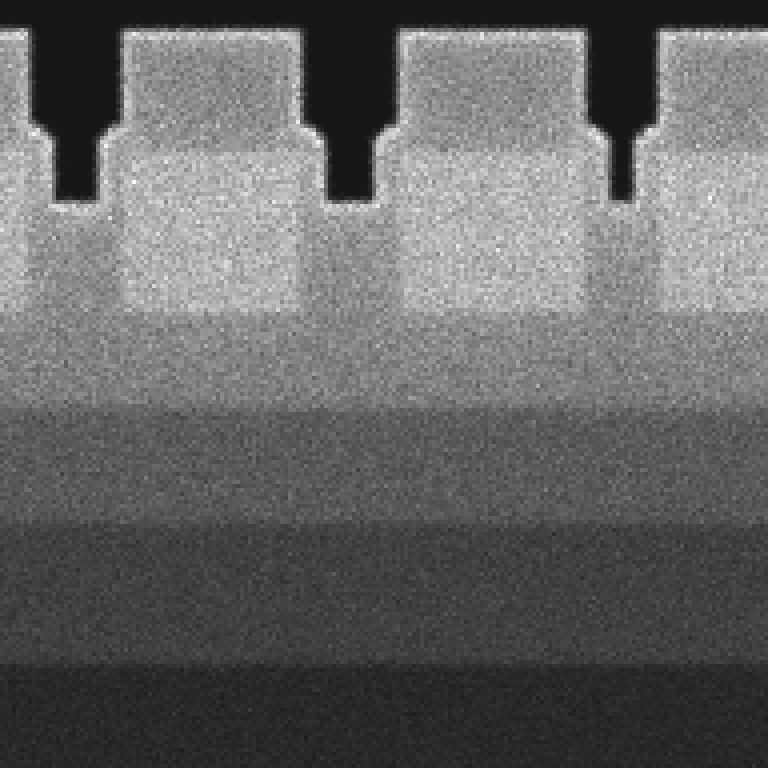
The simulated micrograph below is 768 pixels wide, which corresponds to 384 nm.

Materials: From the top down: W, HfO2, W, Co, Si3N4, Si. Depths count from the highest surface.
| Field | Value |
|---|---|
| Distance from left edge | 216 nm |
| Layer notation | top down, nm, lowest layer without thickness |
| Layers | W 60, HfO2 80, W 48, Co 58, Si3N4 70, Si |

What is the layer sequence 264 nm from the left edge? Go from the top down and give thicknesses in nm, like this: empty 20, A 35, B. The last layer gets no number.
W 60, HfO2 80, W 48, Co 58, Si3N4 70, Si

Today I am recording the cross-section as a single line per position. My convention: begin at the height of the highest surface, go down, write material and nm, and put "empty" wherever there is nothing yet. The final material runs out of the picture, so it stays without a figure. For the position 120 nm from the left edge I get W 60, HfO2 80, W 48, Co 58, Si3N4 70, Si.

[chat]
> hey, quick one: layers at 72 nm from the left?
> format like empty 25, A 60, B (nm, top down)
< W 60, HfO2 80, W 48, Co 58, Si3N4 70, Si